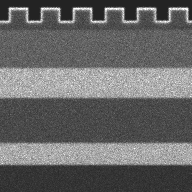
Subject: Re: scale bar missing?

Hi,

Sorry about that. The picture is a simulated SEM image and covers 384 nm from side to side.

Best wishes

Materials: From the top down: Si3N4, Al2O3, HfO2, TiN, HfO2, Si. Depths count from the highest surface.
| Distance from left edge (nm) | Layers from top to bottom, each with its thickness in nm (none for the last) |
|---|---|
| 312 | empty 26, Si3N4 18, Al2O3 76, HfO2 60, TiN 90, HfO2 44, Si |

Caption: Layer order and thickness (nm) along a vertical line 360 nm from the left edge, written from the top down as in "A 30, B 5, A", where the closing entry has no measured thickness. Si3N4 44, Al2O3 76, HfO2 60, TiN 90, HfO2 44, Si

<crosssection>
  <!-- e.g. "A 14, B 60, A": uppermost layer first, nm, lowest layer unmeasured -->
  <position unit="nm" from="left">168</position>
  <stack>Si3N4 44, Al2O3 76, HfO2 60, TiN 90, HfO2 44, Si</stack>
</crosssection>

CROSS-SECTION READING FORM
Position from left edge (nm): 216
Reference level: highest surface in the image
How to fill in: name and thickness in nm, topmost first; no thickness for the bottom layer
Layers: Si3N4 44, Al2O3 76, HfO2 60, TiN 90, HfO2 44, Si